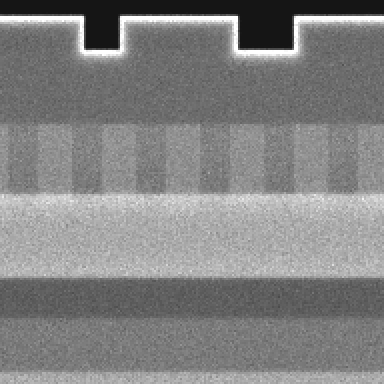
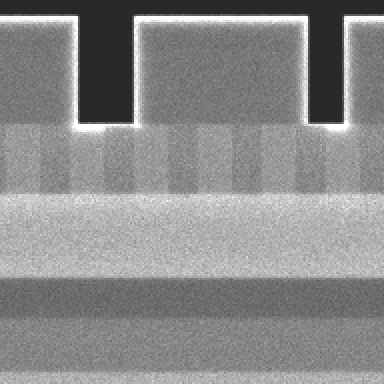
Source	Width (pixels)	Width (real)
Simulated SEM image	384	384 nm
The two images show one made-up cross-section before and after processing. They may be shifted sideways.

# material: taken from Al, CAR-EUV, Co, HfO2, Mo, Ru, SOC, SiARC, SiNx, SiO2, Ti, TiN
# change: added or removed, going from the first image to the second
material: SOC
change: removed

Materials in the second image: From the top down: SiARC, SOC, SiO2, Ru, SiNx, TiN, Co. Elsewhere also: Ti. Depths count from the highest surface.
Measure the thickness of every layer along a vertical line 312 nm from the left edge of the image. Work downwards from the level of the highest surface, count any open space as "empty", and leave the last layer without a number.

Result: empty 108, Ti 70, Ru 84, SiNx 40, TiN 54, Co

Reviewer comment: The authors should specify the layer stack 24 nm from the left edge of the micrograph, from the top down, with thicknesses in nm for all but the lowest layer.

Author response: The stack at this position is SiARC 34, SOC 74, SiO2 70, Ru 84, SiNx 40, TiN 54, Co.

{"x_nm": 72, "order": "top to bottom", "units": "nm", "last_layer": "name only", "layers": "SiARC 34, SOC 74, SiO2 70, Ru 84, SiNx 40, TiN 54, Co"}